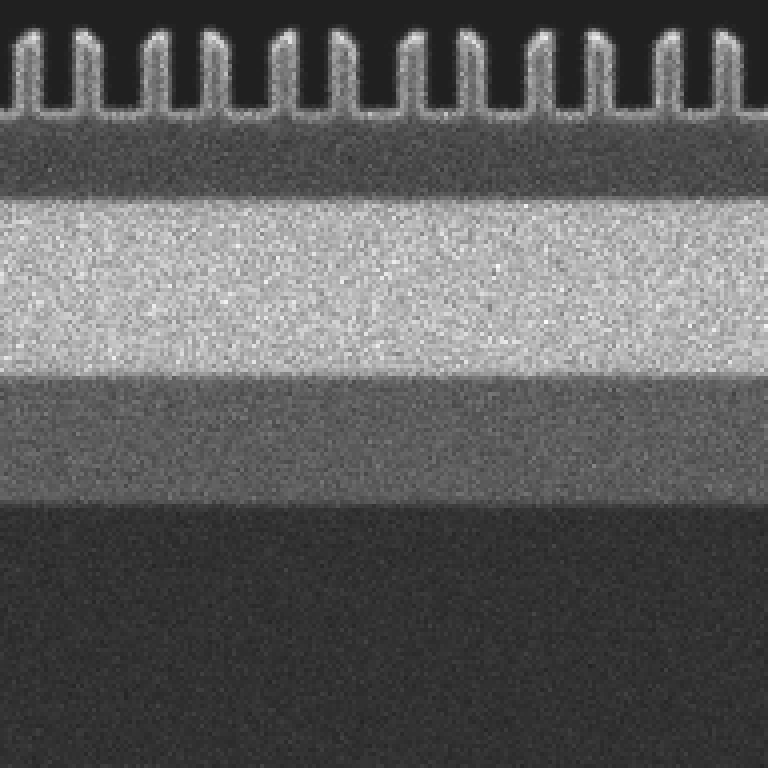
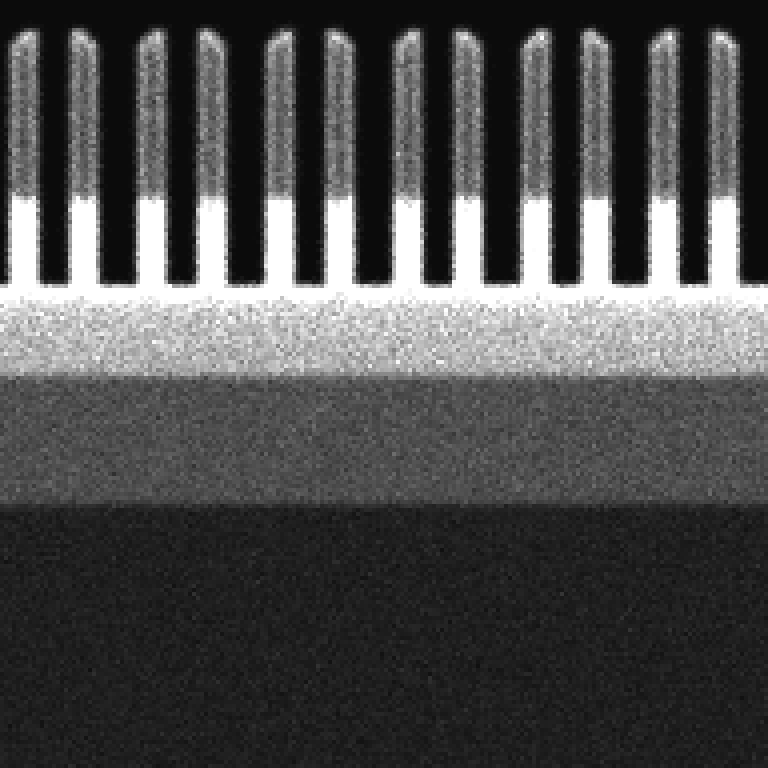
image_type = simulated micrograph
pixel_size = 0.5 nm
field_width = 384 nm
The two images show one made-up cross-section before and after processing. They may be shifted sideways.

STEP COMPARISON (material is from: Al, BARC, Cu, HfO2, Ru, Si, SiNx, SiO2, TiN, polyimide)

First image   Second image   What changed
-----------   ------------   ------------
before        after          HfO2 and TiN, removed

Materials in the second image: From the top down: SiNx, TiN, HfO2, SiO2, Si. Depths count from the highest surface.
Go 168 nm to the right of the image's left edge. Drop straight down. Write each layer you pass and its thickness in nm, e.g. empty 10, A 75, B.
SiNx 40, TiN 44, HfO2 88, SiO2 64, Si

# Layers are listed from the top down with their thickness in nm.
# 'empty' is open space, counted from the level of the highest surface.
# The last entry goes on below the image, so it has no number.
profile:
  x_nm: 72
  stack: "empty 4, SiNx 36, TiN 44, HfO2 88, SiO2 64, Si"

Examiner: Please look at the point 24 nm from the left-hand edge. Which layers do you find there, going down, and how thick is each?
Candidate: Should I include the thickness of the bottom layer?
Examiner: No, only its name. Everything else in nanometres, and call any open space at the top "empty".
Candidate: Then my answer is empty 128, HfO2 44, SiO2 64, Si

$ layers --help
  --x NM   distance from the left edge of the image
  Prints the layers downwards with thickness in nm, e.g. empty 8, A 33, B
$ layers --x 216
empty 128, HfO2 44, SiO2 64, Si